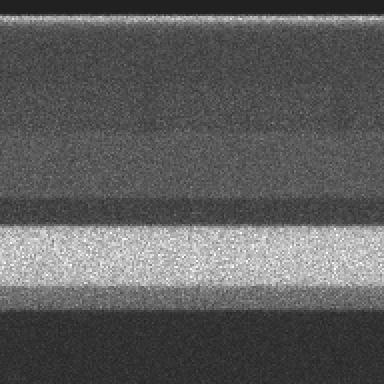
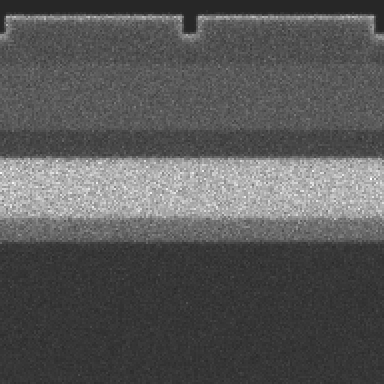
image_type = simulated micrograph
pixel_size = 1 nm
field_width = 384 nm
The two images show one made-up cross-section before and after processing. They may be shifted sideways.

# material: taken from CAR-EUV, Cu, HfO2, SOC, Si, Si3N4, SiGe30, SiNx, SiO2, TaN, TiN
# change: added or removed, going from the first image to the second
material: SOC
change: removed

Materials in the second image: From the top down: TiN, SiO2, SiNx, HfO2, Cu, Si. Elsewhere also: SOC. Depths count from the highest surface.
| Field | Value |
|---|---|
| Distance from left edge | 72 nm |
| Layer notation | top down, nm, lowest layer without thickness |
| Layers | TiN 48, SiO2 66, SiNx 28, HfO2 60, Cu 24, Si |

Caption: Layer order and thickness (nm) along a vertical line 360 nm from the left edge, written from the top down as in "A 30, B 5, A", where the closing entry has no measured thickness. TiN 48, SiO2 66, SiNx 28, HfO2 60, Cu 24, Si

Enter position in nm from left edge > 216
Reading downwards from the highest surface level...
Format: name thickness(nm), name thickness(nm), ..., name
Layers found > TiN 48, SiO2 66, SiNx 28, HfO2 60, Cu 24, Si